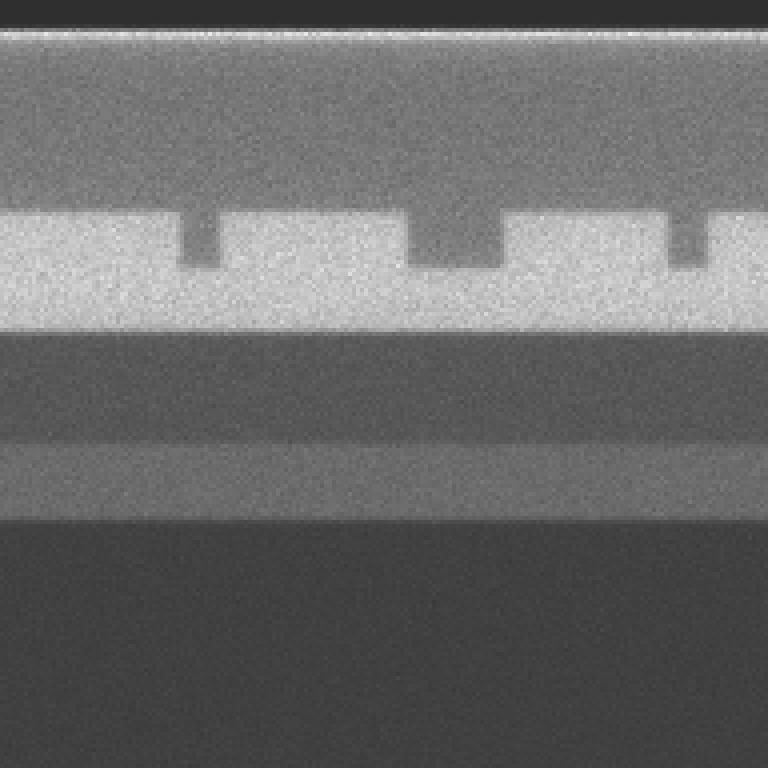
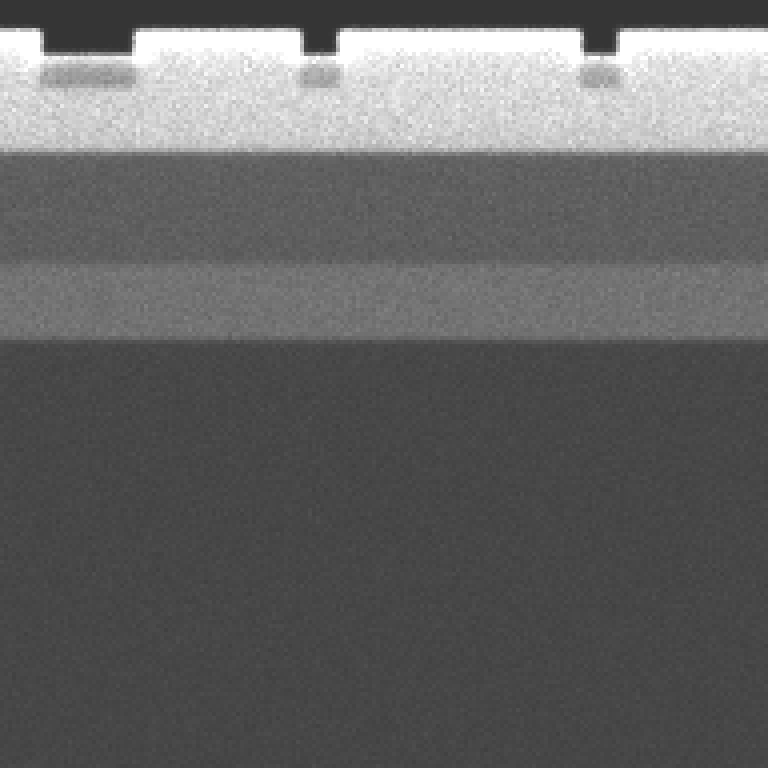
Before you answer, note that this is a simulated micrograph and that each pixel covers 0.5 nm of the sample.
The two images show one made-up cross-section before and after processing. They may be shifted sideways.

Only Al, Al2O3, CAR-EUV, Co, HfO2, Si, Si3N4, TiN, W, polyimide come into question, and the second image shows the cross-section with Co removed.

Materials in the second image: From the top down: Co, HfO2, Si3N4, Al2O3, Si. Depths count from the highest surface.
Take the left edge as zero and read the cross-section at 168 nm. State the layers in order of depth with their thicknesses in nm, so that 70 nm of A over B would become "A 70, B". empty 12, Co 16, HfO2 32, Si3N4 56, Al2O3 38, Si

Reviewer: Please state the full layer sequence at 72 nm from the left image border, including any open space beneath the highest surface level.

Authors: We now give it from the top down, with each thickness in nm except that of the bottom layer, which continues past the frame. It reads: HfO2 60, Si3N4 56, Al2O3 38, Si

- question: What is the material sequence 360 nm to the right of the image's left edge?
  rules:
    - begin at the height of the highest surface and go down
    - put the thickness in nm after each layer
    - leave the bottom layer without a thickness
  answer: HfO2 60, Si3N4 56, Al2O3 38, Si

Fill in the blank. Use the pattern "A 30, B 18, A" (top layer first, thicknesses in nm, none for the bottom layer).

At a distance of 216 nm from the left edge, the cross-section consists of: HfO2 60, Si3N4 56, Al2O3 38, Si